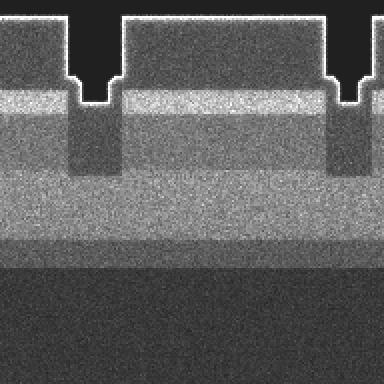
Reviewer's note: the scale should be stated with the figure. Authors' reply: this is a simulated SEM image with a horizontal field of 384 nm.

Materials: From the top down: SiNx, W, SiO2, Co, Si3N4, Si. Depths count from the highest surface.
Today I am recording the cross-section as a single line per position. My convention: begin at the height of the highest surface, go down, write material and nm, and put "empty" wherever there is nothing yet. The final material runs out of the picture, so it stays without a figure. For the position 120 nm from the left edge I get empty 60, SiNx 100, Co 64, Si3N4 28, Si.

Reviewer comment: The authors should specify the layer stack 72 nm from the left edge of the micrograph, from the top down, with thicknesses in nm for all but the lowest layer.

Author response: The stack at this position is empty 60, SiNx 100, Co 64, Si3N4 28, Si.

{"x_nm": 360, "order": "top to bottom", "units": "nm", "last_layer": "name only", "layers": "empty 64, SiNx 96, Co 64, Si3N4 28, Si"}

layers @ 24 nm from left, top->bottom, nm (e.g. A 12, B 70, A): SiNx 74, W 24, SiO2 56, Co 70, Si3N4 28, Si